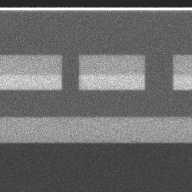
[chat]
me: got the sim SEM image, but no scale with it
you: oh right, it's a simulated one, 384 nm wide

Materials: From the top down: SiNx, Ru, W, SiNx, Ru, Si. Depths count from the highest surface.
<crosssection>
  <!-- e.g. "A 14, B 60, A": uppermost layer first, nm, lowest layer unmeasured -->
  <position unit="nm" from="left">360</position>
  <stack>SiNx 94, Ru 40, W 30, SiNx 54, Ru 52, Si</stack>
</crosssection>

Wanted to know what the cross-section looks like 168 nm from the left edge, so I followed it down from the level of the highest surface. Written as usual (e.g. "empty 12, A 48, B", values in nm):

SiNx 94, Ru 40, W 30, SiNx 54, Ru 52, Si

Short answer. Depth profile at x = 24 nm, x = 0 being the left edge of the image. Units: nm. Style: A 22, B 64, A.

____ SiNx 94, Ru 40, W 30, SiNx 54, Ru 52, Si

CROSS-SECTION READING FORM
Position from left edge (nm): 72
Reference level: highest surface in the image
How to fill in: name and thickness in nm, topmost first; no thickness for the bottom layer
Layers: SiNx 94, Ru 40, W 30, SiNx 54, Ru 52, Si